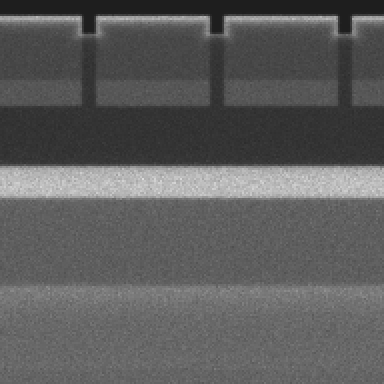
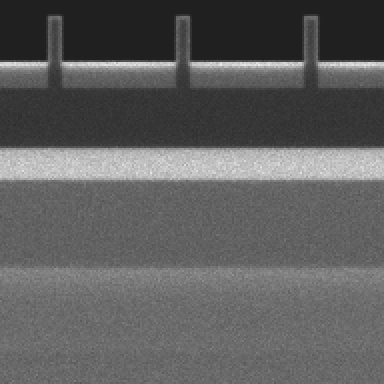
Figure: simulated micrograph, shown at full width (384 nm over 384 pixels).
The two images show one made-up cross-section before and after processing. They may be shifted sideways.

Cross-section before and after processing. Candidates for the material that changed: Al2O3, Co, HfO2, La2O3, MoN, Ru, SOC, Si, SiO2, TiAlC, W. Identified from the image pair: SOC (removed).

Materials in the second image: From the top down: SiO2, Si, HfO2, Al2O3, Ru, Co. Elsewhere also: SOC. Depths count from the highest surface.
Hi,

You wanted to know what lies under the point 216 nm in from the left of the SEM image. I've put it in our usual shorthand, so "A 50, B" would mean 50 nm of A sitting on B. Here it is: empty 46, SiO2 26, Si 60, HfO2 32, Al2O3 88, Ru 84, Co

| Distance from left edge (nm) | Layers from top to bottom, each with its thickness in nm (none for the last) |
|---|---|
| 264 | empty 46, SiO2 26, Si 60, HfO2 32, Al2O3 88, Ru 84, Co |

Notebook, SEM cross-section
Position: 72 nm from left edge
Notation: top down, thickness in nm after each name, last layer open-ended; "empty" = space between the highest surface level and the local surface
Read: empty 46, SiO2 26, Si 60, HfO2 32, Al2O3 88, Ru 84, Co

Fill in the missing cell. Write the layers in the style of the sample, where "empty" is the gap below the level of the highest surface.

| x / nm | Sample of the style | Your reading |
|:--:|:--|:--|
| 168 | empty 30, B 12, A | empty 46, SiO2 26, Si 60, HfO2 32, Al2O3 88, Ru 84, Co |